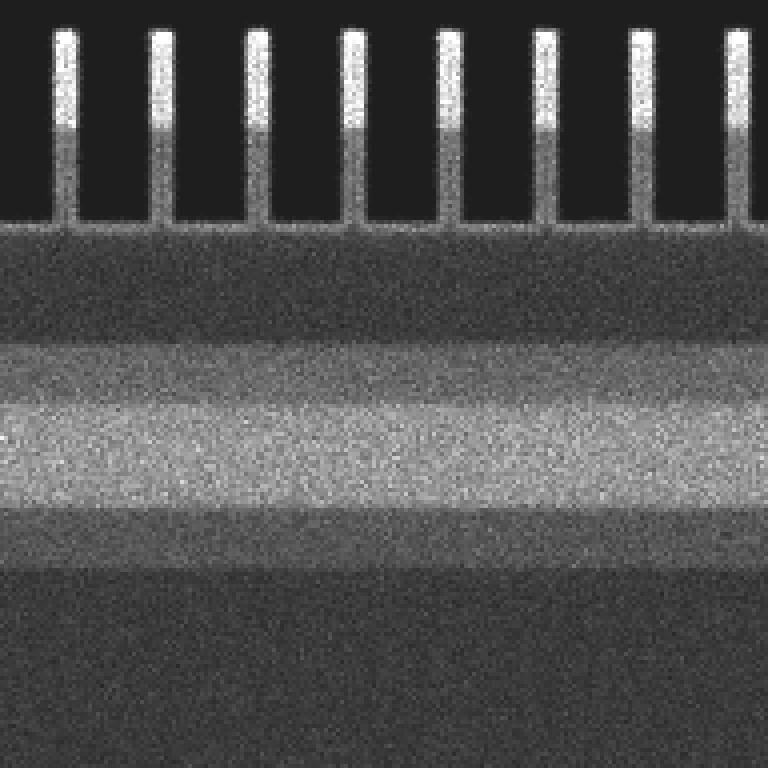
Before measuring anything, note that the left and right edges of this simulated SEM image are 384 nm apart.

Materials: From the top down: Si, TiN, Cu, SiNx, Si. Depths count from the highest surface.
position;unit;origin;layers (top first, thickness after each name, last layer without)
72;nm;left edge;empty 96, Si 60, TiN 30, Cu 52, SiNx 30, Si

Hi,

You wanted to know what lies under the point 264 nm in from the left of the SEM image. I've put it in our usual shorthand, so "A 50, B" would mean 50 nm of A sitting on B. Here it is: empty 96, Si 60, TiN 30, Cu 52, SiNx 30, Si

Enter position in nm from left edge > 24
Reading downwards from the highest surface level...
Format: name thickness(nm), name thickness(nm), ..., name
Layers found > empty 96, Si 60, TiN 30, Cu 52, SiNx 30, Si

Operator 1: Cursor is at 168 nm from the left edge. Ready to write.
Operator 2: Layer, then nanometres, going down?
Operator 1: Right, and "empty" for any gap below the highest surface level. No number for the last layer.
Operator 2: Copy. empty 96, Si 60, TiN 30, Cu 52, SiNx 30, Si